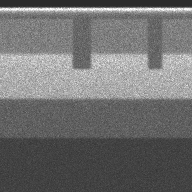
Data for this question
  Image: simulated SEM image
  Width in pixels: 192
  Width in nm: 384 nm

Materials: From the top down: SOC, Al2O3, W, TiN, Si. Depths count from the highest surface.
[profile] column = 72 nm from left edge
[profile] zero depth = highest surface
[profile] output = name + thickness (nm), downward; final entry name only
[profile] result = SOC 22, Al2O3 70, W 90, TiN 78, Si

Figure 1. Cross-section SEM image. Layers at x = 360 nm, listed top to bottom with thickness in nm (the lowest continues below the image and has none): SOC 22, Al2O3 70, W 90, TiN 78, Si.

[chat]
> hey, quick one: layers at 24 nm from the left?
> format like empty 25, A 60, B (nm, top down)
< SOC 22, Al2O3 70, W 90, TiN 78, Si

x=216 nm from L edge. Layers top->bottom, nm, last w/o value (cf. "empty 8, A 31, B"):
SOC 22, Al2O3 70, W 90, TiN 78, Si